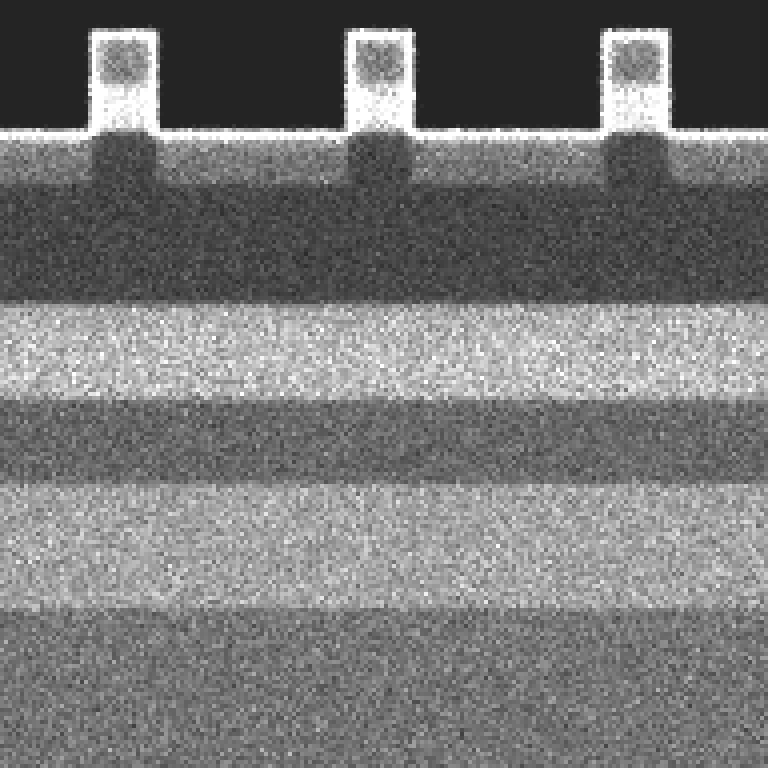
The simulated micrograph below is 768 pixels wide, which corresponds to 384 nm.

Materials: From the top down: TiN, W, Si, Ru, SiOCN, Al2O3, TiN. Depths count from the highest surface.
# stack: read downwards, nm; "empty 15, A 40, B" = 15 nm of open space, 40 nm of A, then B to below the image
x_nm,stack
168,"empty 50, TiN 26, Si 60, Ru 48, SiOCN 42, Al2O3 62, TiN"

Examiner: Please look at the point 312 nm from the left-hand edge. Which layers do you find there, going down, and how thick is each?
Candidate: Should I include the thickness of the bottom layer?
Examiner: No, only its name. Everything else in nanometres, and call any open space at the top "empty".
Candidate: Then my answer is TiN 26, W 24, Si 86, Ru 48, SiOCN 42, Al2O3 62, TiN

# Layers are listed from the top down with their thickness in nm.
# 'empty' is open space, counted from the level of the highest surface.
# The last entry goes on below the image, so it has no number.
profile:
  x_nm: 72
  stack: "TiN 26, W 24, Si 86, Ru 48, SiOCN 42, Al2O3 62, TiN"